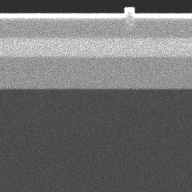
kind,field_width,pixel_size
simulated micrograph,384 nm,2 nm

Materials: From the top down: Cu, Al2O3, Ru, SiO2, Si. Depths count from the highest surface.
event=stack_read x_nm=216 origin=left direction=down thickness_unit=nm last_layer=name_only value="empty 12, Al2O3 48, Ru 38, SiO2 64, Si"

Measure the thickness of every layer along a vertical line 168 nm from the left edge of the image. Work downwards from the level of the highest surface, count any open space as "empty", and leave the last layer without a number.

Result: empty 12, Al2O3 48, Ru 38, SiO2 64, Si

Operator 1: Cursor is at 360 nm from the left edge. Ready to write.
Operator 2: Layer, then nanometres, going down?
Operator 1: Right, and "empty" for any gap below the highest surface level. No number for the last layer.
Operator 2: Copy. empty 12, Al2O3 48, Ru 38, SiO2 64, Si